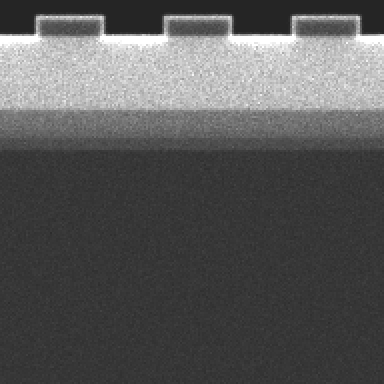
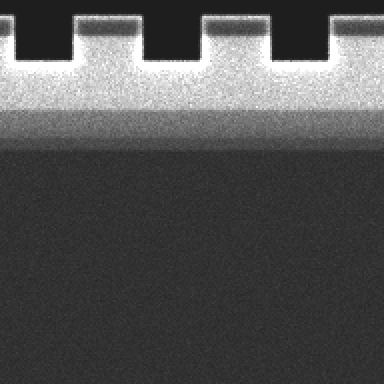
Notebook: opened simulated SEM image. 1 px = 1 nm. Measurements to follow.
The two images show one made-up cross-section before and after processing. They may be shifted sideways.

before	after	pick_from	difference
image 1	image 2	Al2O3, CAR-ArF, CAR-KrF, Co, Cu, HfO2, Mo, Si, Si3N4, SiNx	HfO2 removed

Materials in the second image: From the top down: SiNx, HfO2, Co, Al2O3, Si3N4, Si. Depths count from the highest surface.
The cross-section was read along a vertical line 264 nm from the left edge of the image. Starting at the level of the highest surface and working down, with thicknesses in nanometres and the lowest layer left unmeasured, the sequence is SiNx 20, HfO2 74, Co 20, Al2O3 8, Si3N4 12, Si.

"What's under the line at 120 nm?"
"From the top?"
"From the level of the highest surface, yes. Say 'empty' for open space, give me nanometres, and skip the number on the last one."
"SiNx 20, HfO2 74, Co 20, Al2O3 8, Si3N4 12, Si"